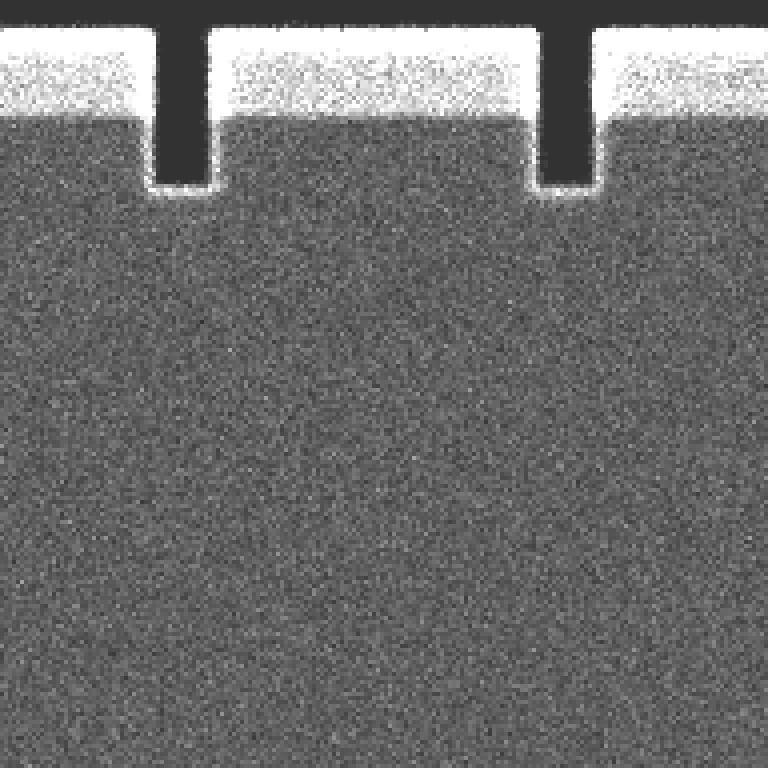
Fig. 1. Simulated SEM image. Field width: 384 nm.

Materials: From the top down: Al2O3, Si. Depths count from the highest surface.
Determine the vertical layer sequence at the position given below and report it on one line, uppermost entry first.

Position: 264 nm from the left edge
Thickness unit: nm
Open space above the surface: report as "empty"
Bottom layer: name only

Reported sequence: Al2O3 42, Si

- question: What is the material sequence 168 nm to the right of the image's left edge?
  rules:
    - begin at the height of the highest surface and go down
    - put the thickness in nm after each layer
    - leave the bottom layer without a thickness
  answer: Al2O3 42, Si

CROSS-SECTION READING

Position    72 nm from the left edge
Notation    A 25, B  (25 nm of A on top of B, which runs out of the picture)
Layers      Al2O3 42, Si